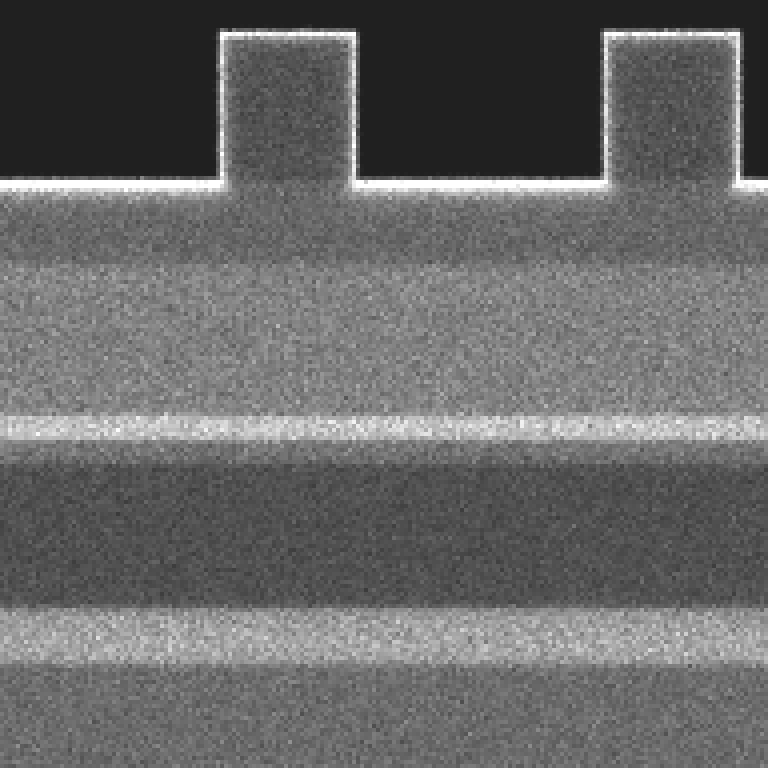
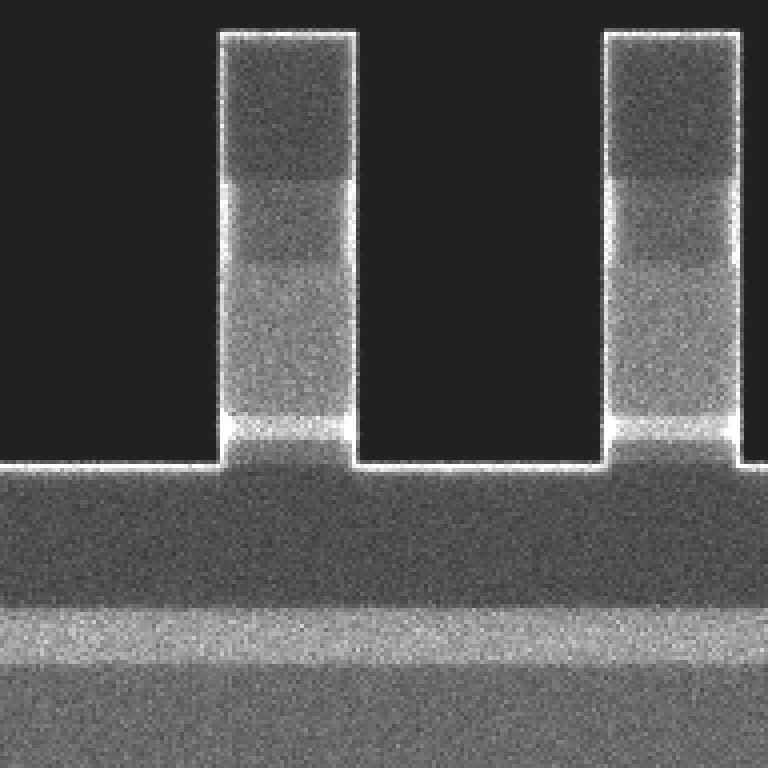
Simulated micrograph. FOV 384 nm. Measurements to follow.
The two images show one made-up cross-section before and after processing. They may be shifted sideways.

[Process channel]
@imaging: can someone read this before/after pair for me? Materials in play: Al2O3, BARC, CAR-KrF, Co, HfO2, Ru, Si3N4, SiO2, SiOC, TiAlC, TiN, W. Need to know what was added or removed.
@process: Co and HfO2 and Ru and SiO2 removed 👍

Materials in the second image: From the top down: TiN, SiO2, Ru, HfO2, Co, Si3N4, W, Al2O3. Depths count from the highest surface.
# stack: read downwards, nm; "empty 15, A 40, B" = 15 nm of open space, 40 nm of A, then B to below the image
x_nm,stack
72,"empty 216, Si3N4 72, W 28, Al2O3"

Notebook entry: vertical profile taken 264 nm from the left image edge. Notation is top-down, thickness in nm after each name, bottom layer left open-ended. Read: empty 216, Si3N4 72, W 28, Al2O3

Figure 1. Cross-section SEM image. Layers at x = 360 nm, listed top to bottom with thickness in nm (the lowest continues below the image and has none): TiN 74, SiO2 42, Ru 76, HfO2 12, Co 12, Si3N4 72, W 28, Al2O3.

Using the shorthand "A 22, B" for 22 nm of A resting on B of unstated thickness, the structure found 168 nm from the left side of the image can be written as TiN 74, SiO2 42, Ru 76, HfO2 12, Co 12, Si3N4 72, W 28, Al2O3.